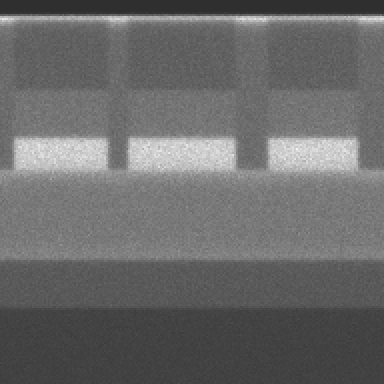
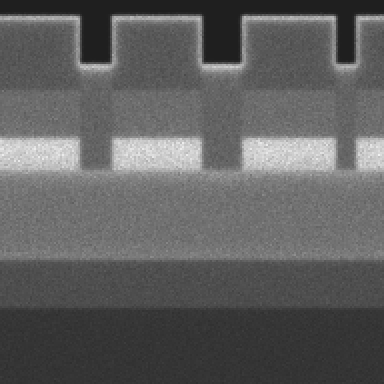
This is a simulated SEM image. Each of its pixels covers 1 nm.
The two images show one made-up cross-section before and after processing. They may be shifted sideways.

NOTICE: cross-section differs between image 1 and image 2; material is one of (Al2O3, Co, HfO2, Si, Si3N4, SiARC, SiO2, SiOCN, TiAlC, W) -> removed: SiO2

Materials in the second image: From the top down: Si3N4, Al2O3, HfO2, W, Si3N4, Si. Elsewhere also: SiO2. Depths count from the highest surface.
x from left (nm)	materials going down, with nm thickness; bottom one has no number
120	Si3N4 74, Al2O3 48, HfO2 32, W 90, Si3N4 48, Si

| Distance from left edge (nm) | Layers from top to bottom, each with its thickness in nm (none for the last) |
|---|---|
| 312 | Si3N4 74, Al2O3 48, HfO2 32, W 90, Si3N4 48, Si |